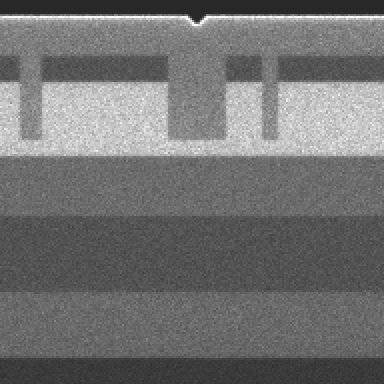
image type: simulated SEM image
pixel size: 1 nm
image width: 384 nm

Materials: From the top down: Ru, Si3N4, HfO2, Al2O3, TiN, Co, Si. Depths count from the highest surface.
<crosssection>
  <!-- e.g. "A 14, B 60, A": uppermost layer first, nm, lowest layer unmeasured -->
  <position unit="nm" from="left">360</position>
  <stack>Ru 40, Si3N4 26, HfO2 74, Al2O3 60, TiN 76, Co 66, Si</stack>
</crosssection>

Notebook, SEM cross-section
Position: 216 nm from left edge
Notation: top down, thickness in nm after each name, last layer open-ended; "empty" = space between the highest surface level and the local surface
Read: Ru 124, HfO2 16, Al2O3 60, TiN 76, Co 66, Si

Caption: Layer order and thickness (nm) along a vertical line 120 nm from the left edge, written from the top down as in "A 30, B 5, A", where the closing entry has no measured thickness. Ru 40, Si3N4 26, HfO2 74, Al2O3 60, TiN 76, Co 66, Si